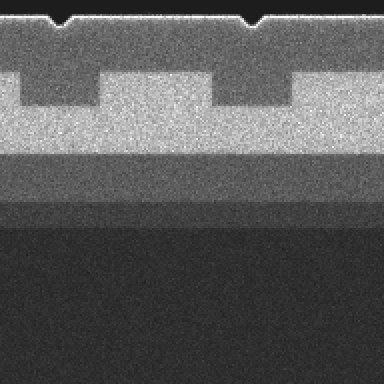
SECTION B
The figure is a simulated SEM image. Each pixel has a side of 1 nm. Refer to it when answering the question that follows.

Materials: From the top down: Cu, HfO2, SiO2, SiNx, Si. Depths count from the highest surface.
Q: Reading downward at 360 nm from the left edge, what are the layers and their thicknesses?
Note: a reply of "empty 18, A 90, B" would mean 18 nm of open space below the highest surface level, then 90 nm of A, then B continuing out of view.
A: Cu 56, HfO2 82, SiO2 48, SiNx 26, Si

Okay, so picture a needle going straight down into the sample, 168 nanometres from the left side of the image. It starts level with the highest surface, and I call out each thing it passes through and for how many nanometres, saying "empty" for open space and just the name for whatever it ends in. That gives Cu 56, HfO2 82, SiO2 48, SiNx 26, Si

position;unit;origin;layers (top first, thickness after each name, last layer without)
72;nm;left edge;Cu 90, HfO2 48, SiO2 48, SiNx 26, Si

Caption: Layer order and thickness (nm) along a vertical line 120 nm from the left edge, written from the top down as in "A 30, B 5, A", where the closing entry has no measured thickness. Cu 56, HfO2 82, SiO2 48, SiNx 26, Si